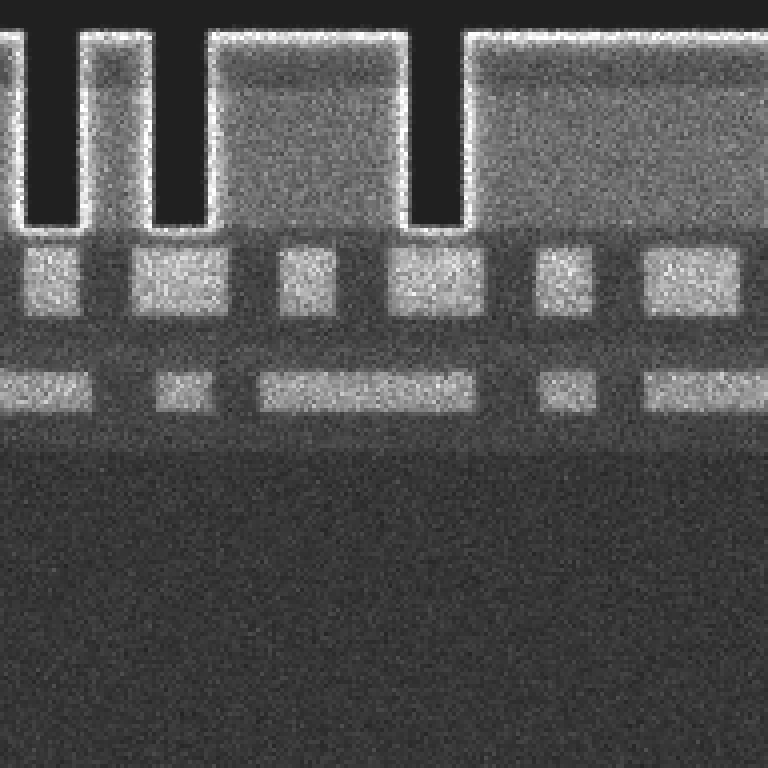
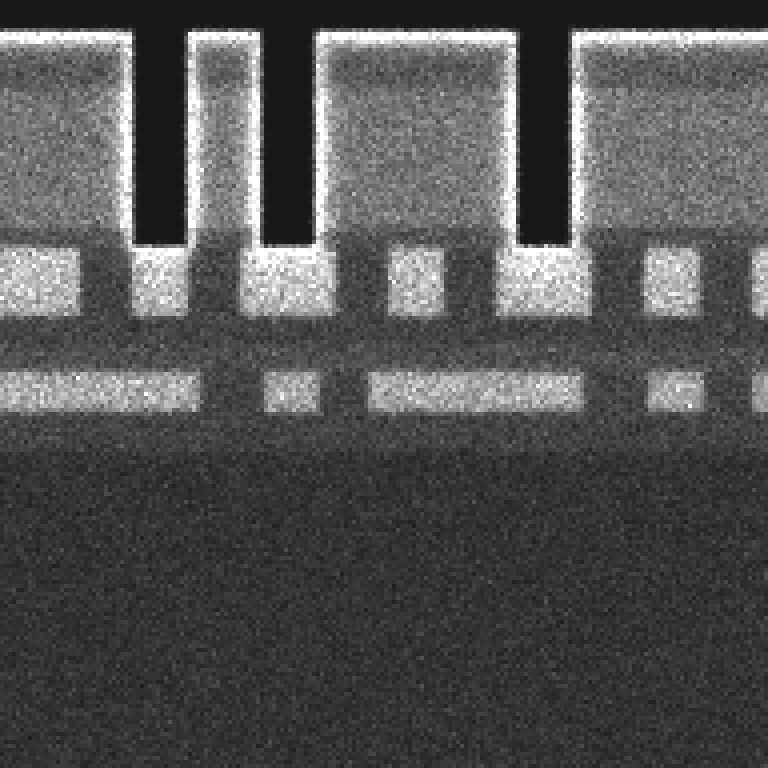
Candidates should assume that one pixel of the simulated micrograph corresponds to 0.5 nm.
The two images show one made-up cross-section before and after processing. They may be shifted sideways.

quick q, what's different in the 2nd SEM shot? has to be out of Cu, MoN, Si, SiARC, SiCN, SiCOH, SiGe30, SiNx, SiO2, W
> SiNx removed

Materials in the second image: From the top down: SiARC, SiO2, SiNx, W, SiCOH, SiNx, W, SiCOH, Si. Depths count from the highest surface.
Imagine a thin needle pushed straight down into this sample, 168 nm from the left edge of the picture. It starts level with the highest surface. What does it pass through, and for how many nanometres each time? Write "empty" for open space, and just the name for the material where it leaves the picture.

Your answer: SiARC 28, SiO2 70, SiNx 10, SiCOH 48, SiNx 14, SiCOH 40, Si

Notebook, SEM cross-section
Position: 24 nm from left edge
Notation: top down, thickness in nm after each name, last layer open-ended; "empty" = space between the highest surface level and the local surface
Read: SiARC 28, SiO2 70, SiNx 10, W 34, SiCOH 14, SiNx 14, W 20, SiCOH 20, Si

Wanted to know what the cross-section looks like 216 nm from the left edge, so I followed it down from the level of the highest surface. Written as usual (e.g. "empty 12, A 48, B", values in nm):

SiARC 28, SiO2 70, SiNx 10, W 34, SiCOH 14, SiNx 14, W 20, SiCOH 20, Si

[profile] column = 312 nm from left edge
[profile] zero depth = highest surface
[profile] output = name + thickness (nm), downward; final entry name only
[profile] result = SiARC 28, SiO2 70, SiNx 10, SiCOH 48, SiNx 14, SiCOH 40, Si